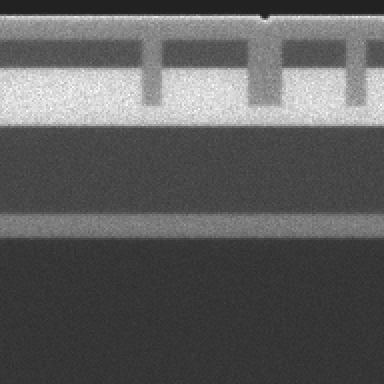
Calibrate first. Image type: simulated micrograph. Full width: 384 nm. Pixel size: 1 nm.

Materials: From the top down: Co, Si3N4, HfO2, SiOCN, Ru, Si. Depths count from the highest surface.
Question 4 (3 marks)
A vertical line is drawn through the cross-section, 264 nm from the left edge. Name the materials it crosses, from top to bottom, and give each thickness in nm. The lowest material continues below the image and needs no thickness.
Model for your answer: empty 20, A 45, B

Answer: empty 4, Co 86, HfO2 20, SiOCN 88, Ru 24, Si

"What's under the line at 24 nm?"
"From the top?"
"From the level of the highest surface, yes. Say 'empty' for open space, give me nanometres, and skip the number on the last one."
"Co 24, Si3N4 28, HfO2 58, SiOCN 88, Ru 24, Si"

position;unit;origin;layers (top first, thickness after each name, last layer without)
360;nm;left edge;Co 90, HfO2 20, SiOCN 88, Ru 24, Si